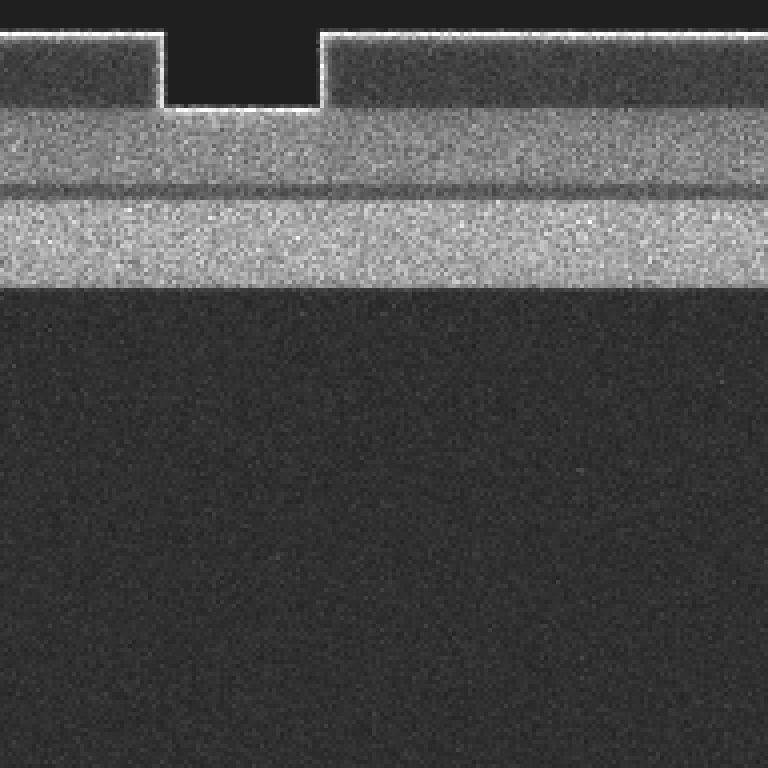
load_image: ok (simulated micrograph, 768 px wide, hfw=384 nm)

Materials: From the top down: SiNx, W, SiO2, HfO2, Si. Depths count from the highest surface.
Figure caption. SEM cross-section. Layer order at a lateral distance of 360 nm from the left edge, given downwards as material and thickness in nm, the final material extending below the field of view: SiNx 38, W 38, SiO2 8, HfO2 44, Si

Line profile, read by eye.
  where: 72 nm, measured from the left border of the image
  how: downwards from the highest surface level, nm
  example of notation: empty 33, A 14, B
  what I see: SiNx 38, W 38, SiO2 8, HfO2 44, Si